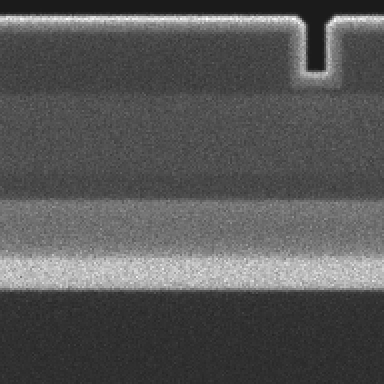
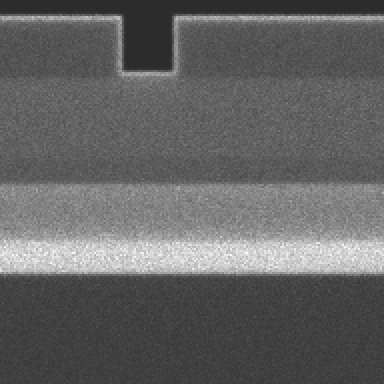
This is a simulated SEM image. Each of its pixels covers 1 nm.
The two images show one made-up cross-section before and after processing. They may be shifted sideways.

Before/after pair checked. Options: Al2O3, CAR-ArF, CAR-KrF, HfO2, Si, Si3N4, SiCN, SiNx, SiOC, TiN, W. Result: removed Al2O3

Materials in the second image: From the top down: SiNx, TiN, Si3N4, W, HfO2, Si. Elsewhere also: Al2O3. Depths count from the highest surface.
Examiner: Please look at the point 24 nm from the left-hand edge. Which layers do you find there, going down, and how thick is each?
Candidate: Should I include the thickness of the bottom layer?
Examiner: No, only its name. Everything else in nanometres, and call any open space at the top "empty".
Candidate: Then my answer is SiNx 62, TiN 80, Si3N4 26, W 58, HfO2 32, Si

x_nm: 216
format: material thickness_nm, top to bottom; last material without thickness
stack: SiNx 62, TiN 80, Si3N4 26, W 58, HfO2 32, Si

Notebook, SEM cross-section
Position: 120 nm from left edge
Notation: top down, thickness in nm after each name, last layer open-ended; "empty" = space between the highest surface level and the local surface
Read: SiNx 62, TiN 80, Si3N4 26, W 58, HfO2 32, Si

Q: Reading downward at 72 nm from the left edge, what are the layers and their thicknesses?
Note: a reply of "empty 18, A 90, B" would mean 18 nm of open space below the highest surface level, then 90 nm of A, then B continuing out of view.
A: SiNx 62, TiN 80, Si3N4 26, W 58, HfO2 32, Si